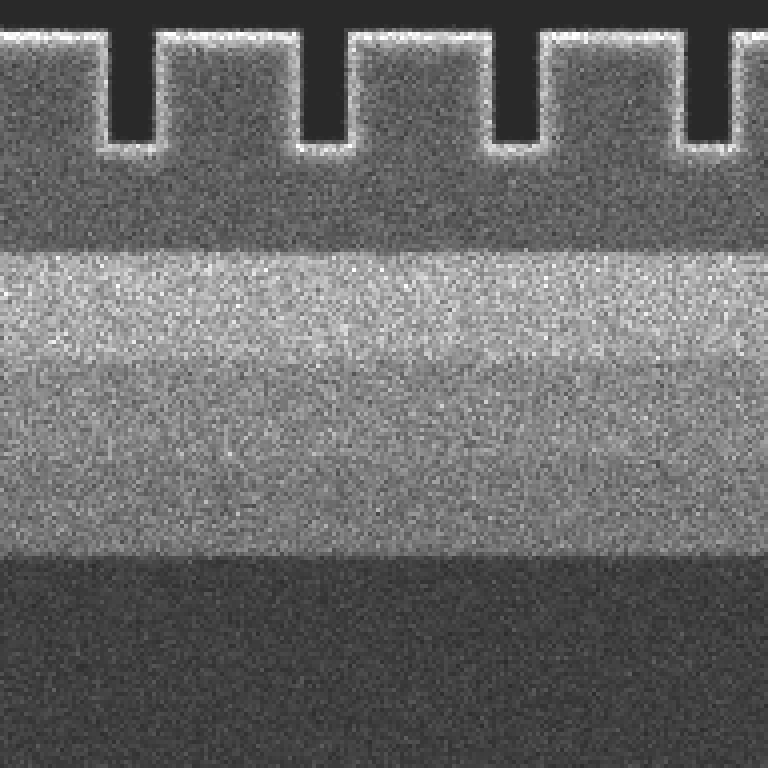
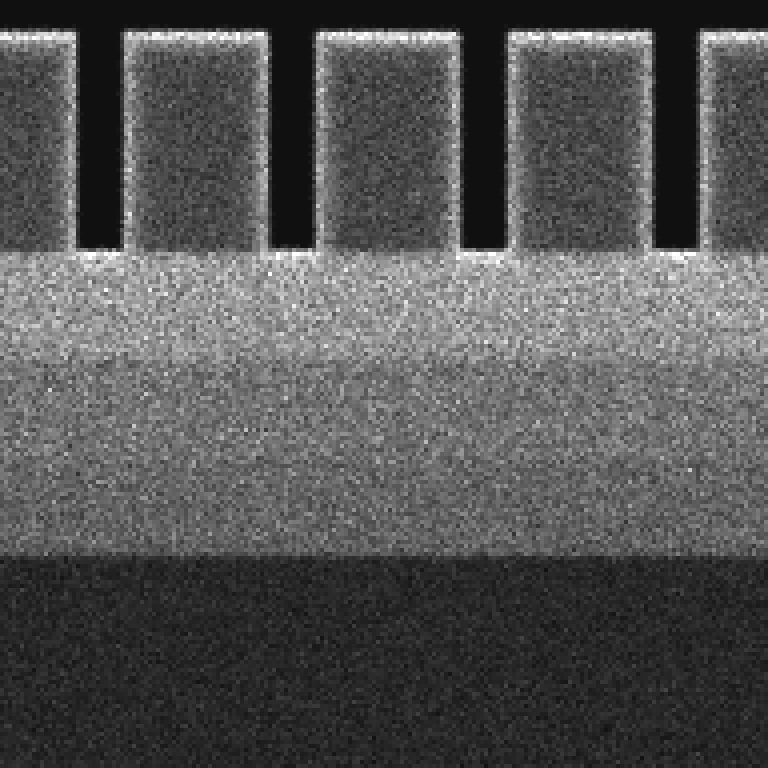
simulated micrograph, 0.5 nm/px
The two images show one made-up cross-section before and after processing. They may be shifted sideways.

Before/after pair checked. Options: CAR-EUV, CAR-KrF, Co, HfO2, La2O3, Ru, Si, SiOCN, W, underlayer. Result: removed underlayer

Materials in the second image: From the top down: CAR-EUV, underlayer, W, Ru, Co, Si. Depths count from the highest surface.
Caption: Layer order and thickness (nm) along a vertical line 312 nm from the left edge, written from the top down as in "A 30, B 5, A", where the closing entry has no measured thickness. CAR-EUV 56, underlayer 54, W 54, Ru 50, Co 48, Si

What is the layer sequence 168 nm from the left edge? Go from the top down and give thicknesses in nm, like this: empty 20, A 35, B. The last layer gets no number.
CAR-EUV 56, underlayer 54, W 54, Ru 50, Co 48, Si